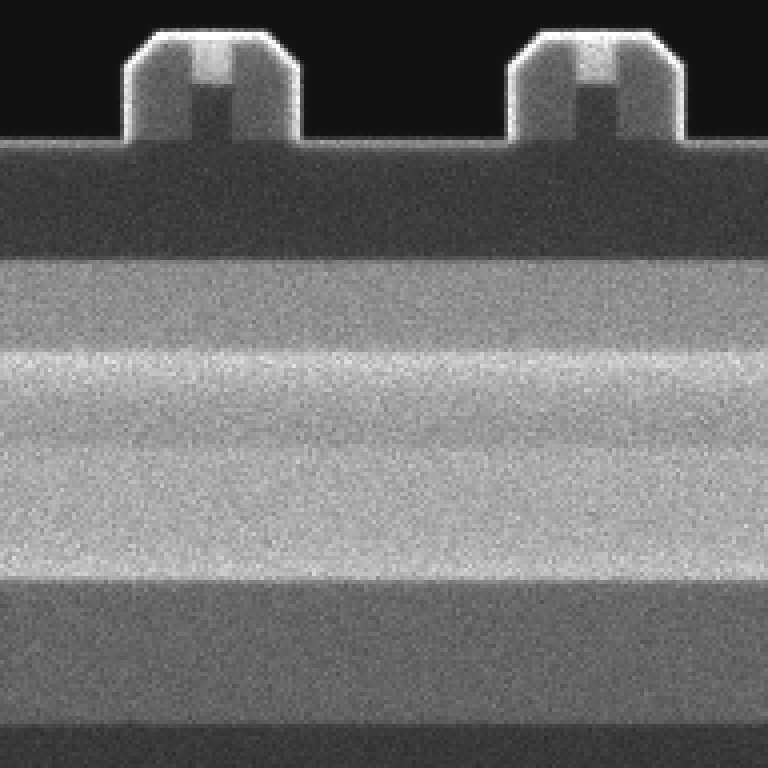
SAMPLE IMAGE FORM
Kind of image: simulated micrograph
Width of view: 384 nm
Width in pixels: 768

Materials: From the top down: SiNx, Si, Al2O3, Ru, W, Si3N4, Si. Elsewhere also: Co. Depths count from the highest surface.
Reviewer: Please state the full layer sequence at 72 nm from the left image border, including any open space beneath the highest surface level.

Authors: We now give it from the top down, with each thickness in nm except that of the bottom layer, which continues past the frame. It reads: empty 6, SiNx 48, Si 60, Al2O3 46, Ru 48, W 66, Si3N4 72, Si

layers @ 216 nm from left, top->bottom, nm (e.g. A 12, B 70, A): empty 54, Si 60, Al2O3 46, Ru 48, W 66, Si3N4 72, Si